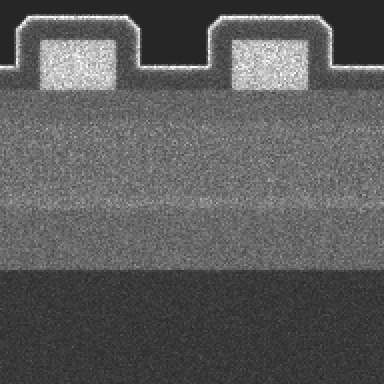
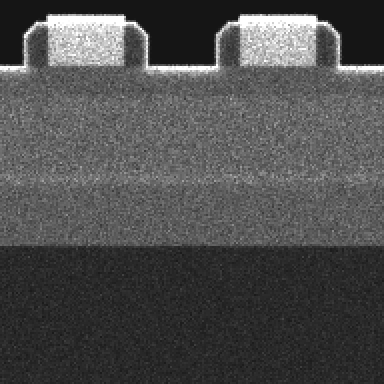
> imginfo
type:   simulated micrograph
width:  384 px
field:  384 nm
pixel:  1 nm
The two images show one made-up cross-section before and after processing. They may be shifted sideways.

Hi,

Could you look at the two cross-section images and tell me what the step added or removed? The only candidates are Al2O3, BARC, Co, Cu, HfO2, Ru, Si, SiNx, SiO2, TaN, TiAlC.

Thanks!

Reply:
removed SiNx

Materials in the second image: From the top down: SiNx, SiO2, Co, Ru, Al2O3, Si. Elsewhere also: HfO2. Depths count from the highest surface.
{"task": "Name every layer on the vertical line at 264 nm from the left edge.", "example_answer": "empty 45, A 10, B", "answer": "HfO2 50, SiO2 30, Co 78, Ru 10, Al2O3 62, Si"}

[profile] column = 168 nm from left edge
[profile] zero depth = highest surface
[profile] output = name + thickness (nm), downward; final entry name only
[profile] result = empty 50, SiO2 30, Co 78, Ru 10, Al2O3 62, Si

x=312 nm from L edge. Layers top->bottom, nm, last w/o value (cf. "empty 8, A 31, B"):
HfO2 50, SiO2 30, Co 78, Ru 10, Al2O3 62, Si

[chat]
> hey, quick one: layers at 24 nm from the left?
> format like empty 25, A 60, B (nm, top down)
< empty 18, SiNx 32, SiO2 30, Co 78, Ru 10, Al2O3 62, Si